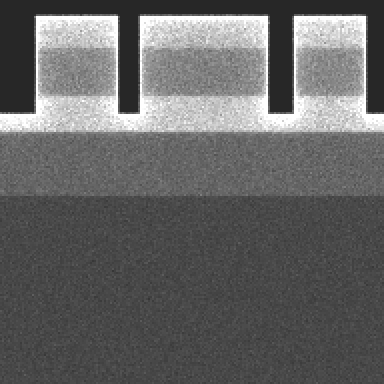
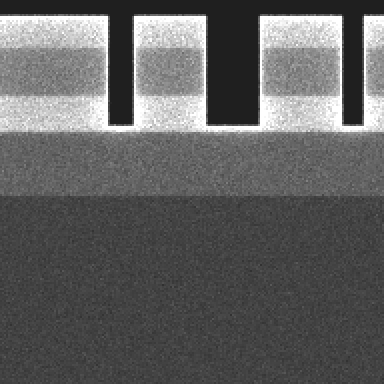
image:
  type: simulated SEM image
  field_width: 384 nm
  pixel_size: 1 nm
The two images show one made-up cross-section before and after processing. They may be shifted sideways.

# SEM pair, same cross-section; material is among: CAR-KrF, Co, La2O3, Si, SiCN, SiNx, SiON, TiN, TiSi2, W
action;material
removed;W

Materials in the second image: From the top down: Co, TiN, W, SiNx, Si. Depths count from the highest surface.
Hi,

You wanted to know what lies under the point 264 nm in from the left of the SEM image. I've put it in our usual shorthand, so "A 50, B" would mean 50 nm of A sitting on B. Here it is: Co 32, TiN 48, W 36, SiNx 64, Si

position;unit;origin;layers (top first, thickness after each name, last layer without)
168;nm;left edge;Co 32, TiN 48, W 36, SiNx 64, Si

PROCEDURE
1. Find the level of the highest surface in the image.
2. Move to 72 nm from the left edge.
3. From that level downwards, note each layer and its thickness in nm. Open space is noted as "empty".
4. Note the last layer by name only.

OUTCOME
Co 32, TiN 48, W 36, SiNx 64, Si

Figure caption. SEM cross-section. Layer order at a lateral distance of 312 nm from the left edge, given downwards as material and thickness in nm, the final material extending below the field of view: Co 32, TiN 48, W 36, SiNx 64, Si